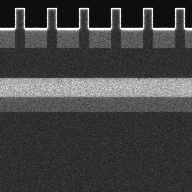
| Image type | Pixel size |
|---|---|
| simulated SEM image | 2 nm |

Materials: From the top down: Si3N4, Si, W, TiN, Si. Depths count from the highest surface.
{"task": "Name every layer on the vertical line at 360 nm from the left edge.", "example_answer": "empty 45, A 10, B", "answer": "Si 140, W 38, TiN 30, Si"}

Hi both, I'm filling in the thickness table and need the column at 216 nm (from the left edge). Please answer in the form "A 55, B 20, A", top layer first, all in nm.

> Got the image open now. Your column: empty 40, Si3N4 40, Si 60, W 38, TiN 30, Si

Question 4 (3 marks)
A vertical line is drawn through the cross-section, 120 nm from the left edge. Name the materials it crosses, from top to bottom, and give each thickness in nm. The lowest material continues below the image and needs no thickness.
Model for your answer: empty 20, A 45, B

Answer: empty 40, Si3N4 40, Si 60, W 38, TiN 30, Si